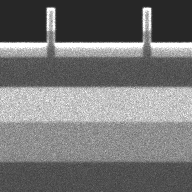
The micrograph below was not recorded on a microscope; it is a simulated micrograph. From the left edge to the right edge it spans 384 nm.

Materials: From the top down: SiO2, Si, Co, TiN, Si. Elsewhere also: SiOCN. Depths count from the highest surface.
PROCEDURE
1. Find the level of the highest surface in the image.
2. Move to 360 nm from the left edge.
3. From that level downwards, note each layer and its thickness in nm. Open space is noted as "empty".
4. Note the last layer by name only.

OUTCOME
empty 70, SiO2 28, Si 60, Co 70, TiN 80, Si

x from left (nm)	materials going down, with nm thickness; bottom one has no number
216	empty 70, SiO2 28, Si 60, Co 70, TiN 80, Si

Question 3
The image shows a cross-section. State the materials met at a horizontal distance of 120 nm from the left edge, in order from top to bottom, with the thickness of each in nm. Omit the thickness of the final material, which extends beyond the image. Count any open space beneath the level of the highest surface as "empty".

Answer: empty 70, SiO2 28, Si 60, Co 70, TiN 80, Si